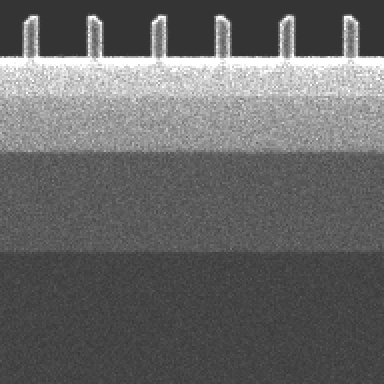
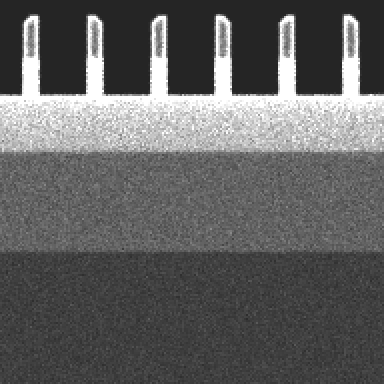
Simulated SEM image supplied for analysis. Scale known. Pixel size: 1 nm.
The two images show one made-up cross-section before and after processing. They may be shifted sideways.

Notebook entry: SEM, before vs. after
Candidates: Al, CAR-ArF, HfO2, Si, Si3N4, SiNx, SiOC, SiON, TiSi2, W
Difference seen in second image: HfO2 removed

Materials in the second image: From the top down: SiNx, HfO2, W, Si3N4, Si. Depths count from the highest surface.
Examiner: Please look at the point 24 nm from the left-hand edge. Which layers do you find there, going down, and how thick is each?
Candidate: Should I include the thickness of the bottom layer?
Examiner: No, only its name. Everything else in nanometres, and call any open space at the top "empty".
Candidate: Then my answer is empty 6, SiNx 36, HfO2 38, W 56, Si3N4 100, Si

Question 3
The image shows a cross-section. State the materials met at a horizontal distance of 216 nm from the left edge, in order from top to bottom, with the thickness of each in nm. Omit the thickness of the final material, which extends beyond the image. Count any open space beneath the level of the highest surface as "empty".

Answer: SiNx 42, HfO2 38, W 56, Si3N4 100, Si